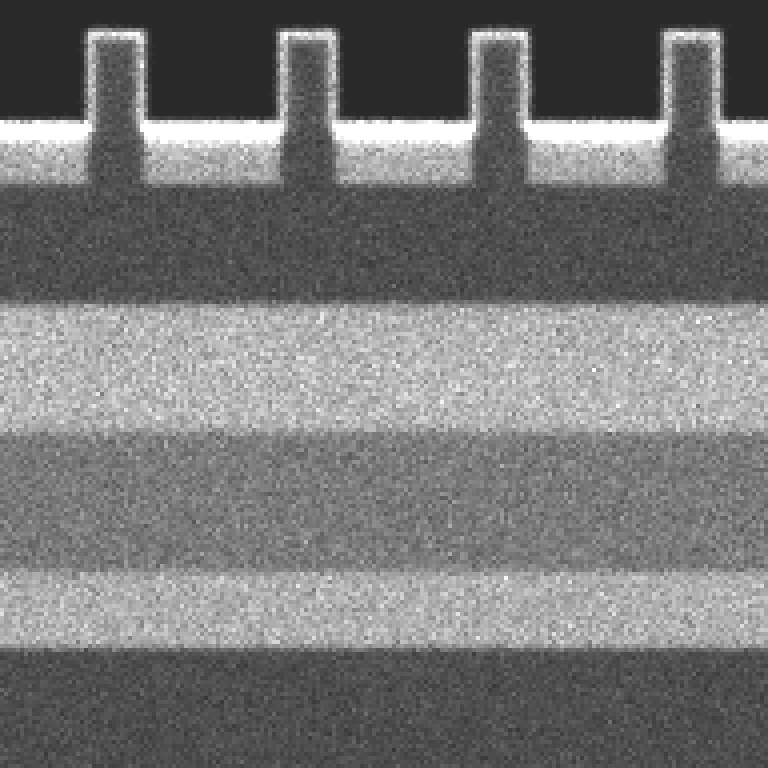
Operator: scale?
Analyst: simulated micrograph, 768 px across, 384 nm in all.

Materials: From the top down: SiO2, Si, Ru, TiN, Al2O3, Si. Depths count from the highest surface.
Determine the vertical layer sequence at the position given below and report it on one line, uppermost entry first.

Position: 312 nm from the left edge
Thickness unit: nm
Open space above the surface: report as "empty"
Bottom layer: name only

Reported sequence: empty 46, SiO2 30, Si 60, Ru 64, TiN 70, Al2O3 38, Si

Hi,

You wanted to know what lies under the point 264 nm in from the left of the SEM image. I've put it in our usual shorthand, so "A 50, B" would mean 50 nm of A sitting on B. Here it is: empty 46, SiO2 30, Si 60, Ru 64, TiN 70, Al2O3 38, Si